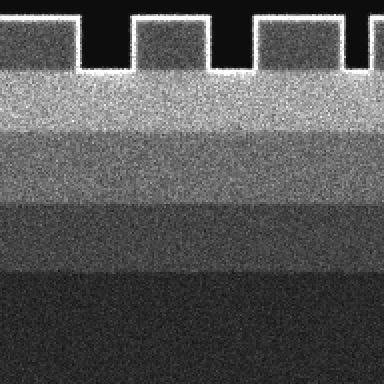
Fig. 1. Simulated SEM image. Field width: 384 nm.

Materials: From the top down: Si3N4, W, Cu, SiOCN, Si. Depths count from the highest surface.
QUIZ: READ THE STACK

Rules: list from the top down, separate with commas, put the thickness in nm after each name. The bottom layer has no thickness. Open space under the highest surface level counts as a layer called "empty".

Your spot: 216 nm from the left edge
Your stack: empty 54, W 62, Cu 72, SiOCN 68, Si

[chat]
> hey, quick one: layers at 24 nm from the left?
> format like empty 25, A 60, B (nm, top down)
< Si3N4 54, W 62, Cu 72, SiOCN 68, Si